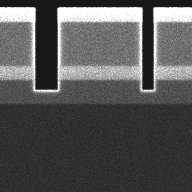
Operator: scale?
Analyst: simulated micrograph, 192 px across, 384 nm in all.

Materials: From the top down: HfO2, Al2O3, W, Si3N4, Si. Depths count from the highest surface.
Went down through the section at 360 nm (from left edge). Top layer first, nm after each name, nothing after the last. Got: HfO2 28, Al2O3 88, W 28, Si3N4 48, Si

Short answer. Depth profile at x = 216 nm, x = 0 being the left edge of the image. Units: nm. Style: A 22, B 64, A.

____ HfO2 28, Al2O3 88, W 28, Si3N4 48, Si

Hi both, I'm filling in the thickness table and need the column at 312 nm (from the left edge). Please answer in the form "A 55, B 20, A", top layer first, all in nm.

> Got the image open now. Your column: HfO2 28, Al2O3 88, W 28, Si3N4 48, Si